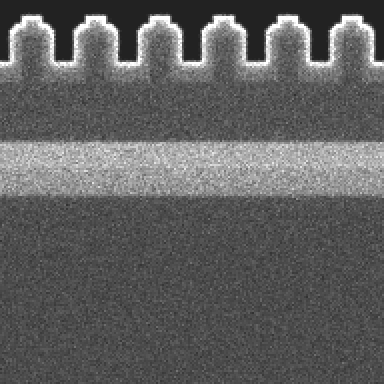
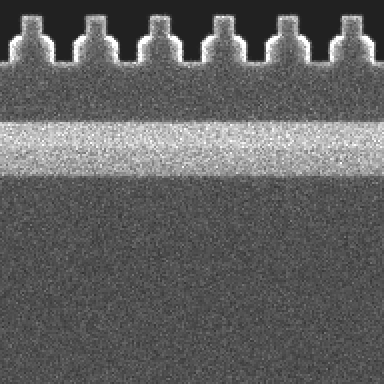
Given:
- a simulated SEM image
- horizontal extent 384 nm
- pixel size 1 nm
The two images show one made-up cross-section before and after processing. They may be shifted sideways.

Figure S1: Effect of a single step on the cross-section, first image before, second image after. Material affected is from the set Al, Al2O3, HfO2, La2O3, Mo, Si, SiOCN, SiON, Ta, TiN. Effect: removed SiOCN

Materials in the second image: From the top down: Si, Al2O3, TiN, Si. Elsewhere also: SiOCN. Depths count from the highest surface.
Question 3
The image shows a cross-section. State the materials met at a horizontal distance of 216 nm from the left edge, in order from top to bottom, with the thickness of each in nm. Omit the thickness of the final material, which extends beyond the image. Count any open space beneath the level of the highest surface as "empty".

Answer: Si 106, Al2O3 26, TiN 28, Si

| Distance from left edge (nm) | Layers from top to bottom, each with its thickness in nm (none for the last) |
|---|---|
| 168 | Si 106, Al2O3 26, TiN 28, Si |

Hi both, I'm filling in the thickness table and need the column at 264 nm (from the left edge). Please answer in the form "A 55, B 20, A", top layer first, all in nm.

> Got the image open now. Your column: empty 46, Si 60, Al2O3 26, TiN 28, Si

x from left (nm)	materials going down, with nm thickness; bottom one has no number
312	empty 46, Si 60, Al2O3 26, TiN 28, Si